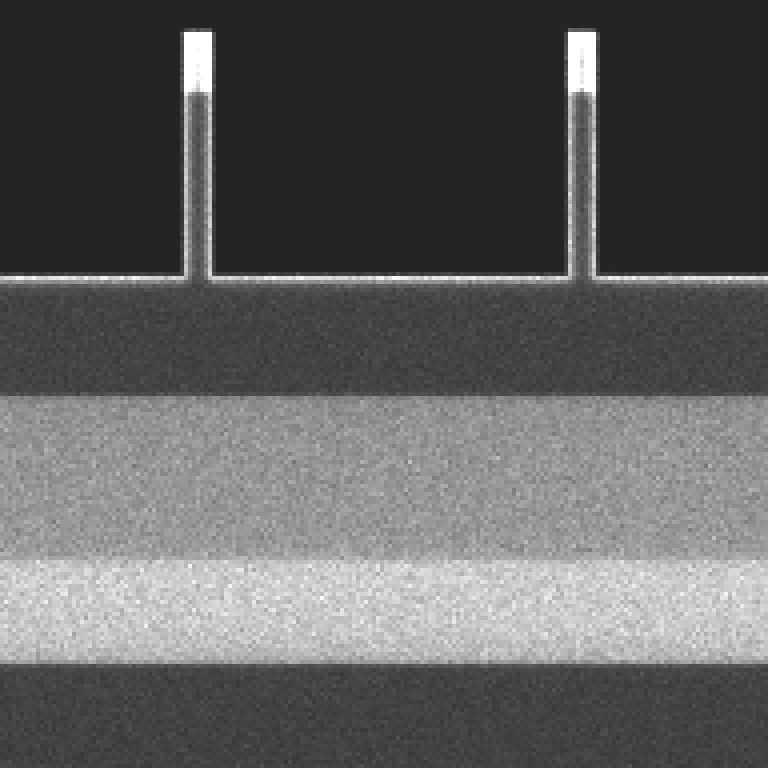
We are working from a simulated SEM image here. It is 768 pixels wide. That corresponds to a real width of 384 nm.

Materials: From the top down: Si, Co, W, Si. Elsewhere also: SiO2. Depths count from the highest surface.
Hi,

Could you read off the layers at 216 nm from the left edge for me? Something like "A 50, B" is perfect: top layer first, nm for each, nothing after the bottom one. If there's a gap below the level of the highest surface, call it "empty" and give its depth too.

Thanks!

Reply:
empty 122, Si 60, Co 82, W 52, Si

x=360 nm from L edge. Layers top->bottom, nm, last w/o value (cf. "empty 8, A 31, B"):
empty 122, Si 60, Co 82, W 52, Si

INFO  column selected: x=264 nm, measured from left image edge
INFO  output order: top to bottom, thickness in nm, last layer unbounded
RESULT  empty 122, Si 60, Co 82, W 52, Si